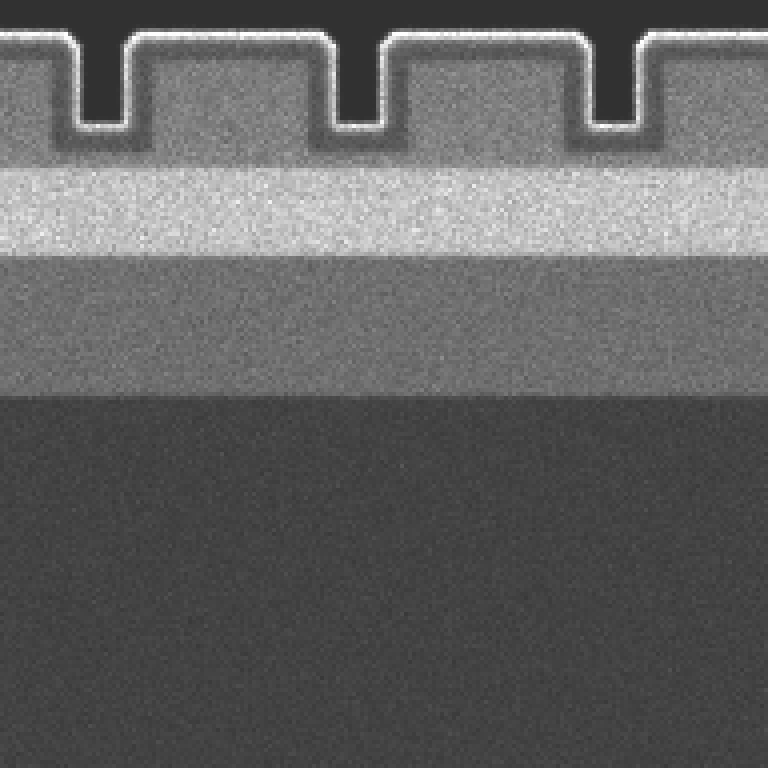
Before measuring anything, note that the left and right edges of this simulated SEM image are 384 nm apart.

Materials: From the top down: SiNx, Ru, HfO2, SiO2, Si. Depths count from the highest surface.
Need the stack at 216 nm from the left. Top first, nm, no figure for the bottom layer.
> SiNx 14, Ru 54, HfO2 44, SiO2 70, Si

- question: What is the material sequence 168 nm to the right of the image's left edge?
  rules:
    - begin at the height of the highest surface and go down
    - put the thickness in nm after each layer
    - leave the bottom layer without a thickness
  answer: empty 46, SiNx 14, Ru 8, HfO2 44, SiO2 70, Si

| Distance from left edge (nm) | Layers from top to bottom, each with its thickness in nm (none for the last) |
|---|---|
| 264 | SiNx 14, Ru 54, HfO2 44, SiO2 70, Si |